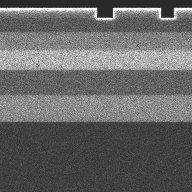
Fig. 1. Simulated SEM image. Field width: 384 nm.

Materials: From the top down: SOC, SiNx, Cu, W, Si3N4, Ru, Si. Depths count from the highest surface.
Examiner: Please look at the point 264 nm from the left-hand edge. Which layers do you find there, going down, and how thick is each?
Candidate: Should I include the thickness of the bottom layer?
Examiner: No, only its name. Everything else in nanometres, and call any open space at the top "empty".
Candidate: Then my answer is SOC 20, SiNx 28, Cu 36, W 40, Si3N4 50, Ru 54, Si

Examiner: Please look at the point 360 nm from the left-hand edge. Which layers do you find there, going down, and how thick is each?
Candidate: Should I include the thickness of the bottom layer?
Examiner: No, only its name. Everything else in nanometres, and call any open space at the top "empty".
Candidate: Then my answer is SOC 20, SiNx 28, Cu 36, W 40, Si3N4 50, Ru 54, Si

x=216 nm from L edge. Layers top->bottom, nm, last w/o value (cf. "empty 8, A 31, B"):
empty 20, SiNx 28, Cu 36, W 40, Si3N4 50, Ru 54, Si